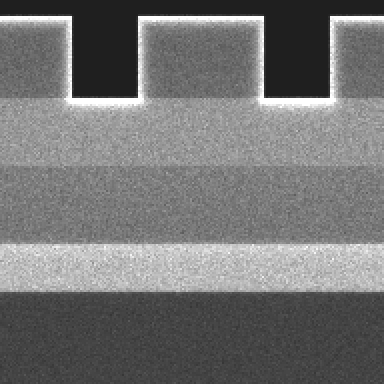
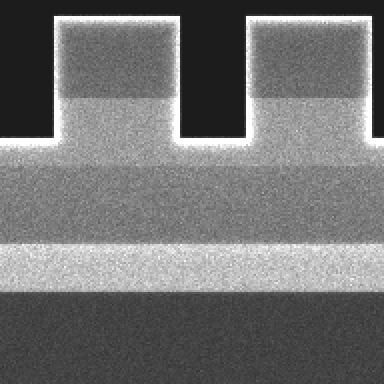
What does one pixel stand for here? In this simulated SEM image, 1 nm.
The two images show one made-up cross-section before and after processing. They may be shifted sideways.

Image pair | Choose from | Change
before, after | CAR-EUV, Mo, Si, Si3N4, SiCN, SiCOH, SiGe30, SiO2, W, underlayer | SiO2 (removed)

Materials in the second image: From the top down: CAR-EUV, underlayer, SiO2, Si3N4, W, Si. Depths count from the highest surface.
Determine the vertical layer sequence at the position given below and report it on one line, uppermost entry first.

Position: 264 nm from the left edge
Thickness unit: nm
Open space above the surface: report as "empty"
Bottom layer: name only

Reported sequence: CAR-EUV 56, underlayer 26, SiO2 68, Si3N4 78, W 48, Si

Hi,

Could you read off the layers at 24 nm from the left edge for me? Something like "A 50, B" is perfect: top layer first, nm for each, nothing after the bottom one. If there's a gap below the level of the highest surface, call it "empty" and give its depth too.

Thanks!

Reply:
empty 122, SiO2 28, Si3N4 78, W 48, Si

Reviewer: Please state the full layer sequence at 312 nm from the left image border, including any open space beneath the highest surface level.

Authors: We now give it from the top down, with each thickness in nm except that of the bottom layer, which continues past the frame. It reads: CAR-EUV 56, underlayer 26, SiO2 68, Si3N4 78, W 48, Si